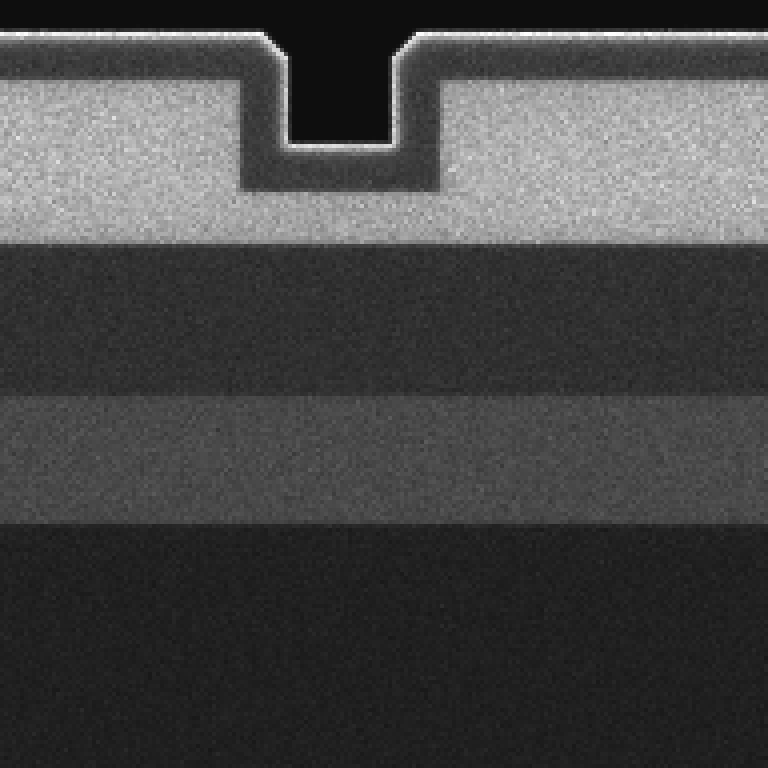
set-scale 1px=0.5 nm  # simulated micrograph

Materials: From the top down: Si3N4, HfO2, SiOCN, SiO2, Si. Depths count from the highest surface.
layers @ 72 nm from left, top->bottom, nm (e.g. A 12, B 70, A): Si3N4 24, HfO2 82, SiOCN 76, SiO2 64, Si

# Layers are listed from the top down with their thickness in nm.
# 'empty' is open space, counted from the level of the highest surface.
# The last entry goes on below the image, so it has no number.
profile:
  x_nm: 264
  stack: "Si3N4 24, HfO2 82, SiOCN 76, SiO2 64, Si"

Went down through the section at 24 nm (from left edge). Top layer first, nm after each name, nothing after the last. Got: Si3N4 24, HfO2 82, SiOCN 76, SiO2 64, Si